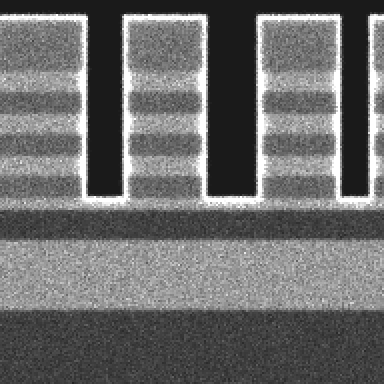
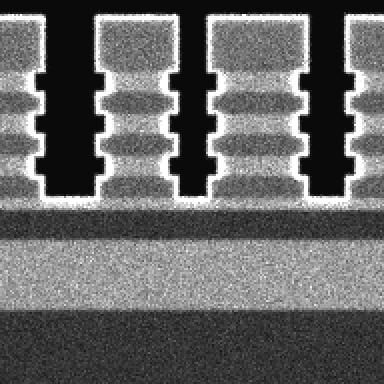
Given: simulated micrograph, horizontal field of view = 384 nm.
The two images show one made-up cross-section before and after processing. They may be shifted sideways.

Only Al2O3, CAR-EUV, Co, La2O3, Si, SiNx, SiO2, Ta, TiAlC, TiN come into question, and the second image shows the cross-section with Al2O3 removed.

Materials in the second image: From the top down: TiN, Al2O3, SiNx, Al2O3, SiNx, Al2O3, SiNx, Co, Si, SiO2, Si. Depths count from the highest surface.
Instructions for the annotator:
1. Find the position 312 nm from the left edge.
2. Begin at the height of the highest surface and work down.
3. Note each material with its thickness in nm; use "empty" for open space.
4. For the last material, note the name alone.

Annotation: empty 182, Co 12, Si 30, SiO2 70, Si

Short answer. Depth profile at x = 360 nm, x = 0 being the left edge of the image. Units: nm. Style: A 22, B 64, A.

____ TiN 56, Al2O3 20, SiNx 22, Al2O3 20, SiNx 22, Al2O3 20, SiNx 22, Co 12, Si 30, SiO2 70, Si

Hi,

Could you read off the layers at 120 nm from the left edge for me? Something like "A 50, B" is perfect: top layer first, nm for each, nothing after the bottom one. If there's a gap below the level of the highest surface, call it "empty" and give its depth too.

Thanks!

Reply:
TiN 56, Al2O3 20, SiNx 22, Al2O3 20, SiNx 22, Al2O3 20, SiNx 22, Co 12, Si 30, SiO2 70, Si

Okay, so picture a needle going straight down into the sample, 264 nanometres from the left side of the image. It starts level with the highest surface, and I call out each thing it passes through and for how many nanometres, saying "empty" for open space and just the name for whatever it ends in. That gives TiN 56, Al2O3 20, SiNx 22, Al2O3 20, SiNx 22, Al2O3 20, SiNx 22, Co 12, Si 30, SiO2 70, Si